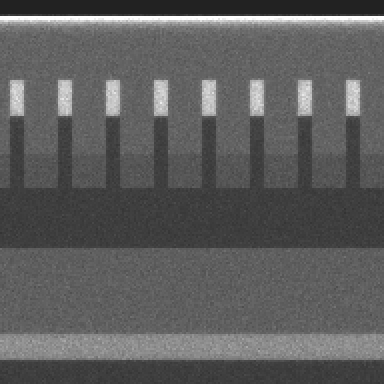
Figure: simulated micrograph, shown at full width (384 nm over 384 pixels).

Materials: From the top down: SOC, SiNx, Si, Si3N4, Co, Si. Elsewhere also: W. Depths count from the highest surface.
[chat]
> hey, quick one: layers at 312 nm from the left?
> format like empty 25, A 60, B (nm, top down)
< SOC 138, SiNx 34, Si 60, Si3N4 86, Co 26, Si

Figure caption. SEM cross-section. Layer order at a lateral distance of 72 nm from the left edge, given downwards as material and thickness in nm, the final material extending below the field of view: SOC 138, SiNx 34, Si 60, Si3N4 86, Co 26, Si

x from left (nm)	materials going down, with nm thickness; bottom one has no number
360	SOC 138, SiNx 34, Si 60, Si3N4 86, Co 26, Si